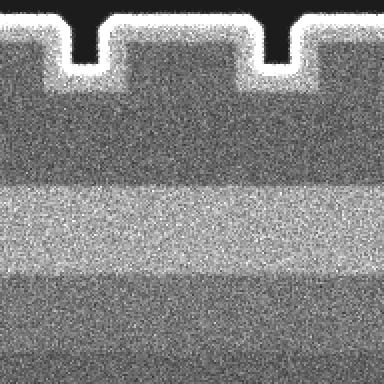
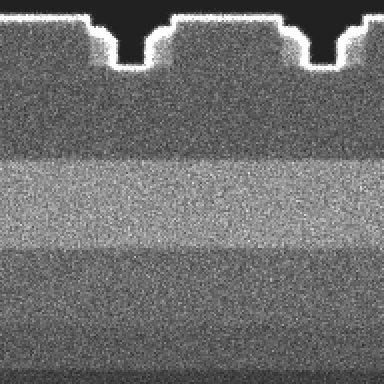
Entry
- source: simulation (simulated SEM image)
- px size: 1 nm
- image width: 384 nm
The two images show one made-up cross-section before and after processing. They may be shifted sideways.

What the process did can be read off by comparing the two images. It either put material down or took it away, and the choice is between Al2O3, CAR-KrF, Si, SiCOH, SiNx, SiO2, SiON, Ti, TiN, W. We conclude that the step removed Al2O3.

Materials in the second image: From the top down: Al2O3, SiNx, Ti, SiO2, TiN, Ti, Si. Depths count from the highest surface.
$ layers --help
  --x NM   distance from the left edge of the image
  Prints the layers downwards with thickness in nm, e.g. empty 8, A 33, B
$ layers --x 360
empty 12, Al2O3 38, SiNx 14, Ti 80, SiO2 88, TiN 78, Ti 44, Si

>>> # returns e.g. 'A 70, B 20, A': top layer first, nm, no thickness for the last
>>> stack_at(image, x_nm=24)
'SiNx 64, Ti 80, SiO2 88, TiN 78, Ti 44, Si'